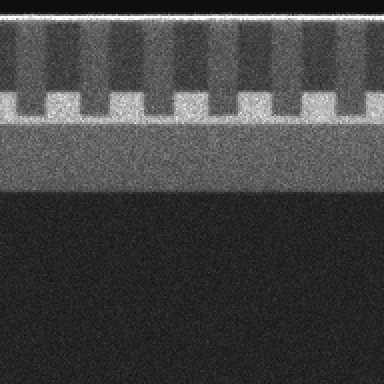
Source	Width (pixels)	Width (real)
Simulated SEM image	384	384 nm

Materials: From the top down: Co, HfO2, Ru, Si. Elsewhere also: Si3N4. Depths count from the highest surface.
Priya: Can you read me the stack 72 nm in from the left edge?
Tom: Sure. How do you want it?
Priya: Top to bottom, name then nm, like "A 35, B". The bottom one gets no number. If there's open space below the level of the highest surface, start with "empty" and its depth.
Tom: Si3N4 76, HfO2 32, Ru 68, Si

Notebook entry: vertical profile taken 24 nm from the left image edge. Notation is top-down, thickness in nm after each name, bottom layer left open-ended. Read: Co 100, HfO2 8, Ru 68, Si